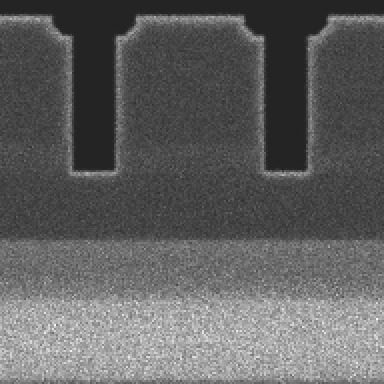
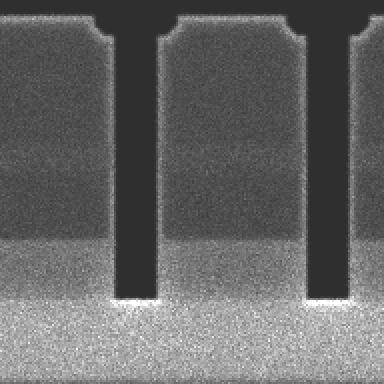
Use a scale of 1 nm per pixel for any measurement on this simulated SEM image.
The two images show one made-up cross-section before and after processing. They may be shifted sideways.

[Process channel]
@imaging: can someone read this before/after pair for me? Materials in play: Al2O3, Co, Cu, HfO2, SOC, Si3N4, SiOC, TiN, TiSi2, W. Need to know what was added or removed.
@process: Si3N4 and W removed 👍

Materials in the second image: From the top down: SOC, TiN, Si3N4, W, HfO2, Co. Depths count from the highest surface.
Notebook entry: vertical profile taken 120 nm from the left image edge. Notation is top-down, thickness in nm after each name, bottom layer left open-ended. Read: empty 284, HfO2 80, Co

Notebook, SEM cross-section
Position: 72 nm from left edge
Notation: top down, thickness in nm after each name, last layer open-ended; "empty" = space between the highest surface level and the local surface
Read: SOC 128, TiN 28, Si3N4 68, W 60, HfO2 80, Co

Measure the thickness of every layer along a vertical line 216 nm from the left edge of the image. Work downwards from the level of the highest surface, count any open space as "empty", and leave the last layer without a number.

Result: SOC 128, TiN 28, Si3N4 68, W 60, HfO2 80, Co